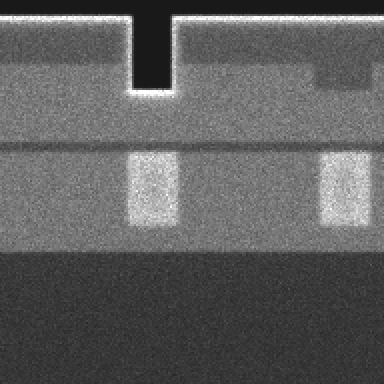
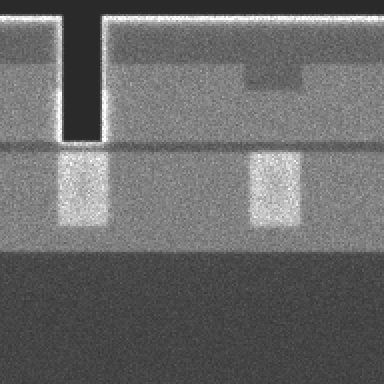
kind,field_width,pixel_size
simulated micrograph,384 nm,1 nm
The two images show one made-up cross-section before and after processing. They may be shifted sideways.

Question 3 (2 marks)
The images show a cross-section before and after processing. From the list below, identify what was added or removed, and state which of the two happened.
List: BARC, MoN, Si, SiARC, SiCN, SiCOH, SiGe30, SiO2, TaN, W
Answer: SiO2 was removed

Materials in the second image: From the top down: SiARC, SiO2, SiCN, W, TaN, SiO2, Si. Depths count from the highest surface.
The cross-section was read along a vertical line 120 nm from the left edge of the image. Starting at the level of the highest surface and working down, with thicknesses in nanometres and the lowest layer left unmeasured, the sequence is SiARC 48, SiO2 78, SiCN 10, SiO2 100, Si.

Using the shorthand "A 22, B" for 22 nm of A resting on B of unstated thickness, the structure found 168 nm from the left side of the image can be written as SiARC 48, SiO2 78, SiCN 10, SiO2 100, Si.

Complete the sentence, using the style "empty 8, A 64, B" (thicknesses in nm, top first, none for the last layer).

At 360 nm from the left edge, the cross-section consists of SiARC 48, SiO2 78, SiCN 10, SiO2 100, Si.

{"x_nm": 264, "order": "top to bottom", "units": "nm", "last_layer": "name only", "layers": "SiARC 74, SiO2 52, SiCN 10, W 66, TaN 8, SiO2 26, Si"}